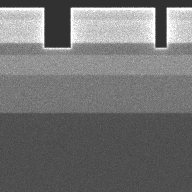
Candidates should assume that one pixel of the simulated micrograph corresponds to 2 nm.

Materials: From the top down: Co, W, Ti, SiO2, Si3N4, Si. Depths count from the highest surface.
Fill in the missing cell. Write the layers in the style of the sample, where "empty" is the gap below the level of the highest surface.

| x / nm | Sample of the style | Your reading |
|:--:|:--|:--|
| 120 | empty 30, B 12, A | empty 80, Ti 14, SiO2 40, Si3N4 76, Si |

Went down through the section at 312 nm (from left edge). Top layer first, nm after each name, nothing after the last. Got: empty 80, Ti 14, SiO2 40, Si3N4 76, Si